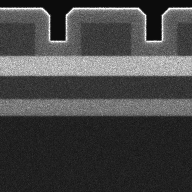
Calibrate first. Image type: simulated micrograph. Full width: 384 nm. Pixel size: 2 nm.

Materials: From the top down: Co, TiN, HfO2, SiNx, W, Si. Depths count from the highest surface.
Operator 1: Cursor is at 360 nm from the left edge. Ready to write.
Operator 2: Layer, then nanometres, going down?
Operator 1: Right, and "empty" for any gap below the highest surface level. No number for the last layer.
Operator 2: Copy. Co 30, TiN 66, HfO2 40, SiNx 46, W 34, Si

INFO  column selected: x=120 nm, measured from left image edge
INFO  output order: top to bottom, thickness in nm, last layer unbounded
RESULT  empty 66, Co 30, HfO2 40, SiNx 46, W 34, Si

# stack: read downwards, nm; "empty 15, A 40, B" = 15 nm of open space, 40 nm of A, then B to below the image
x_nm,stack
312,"empty 66, Co 30, HfO2 40, SiNx 46, W 34, Si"